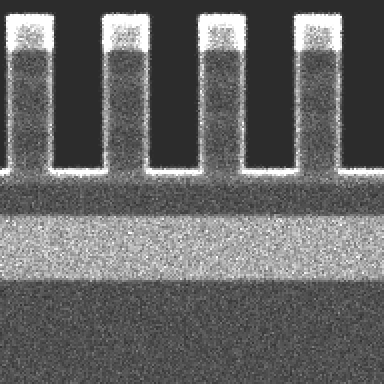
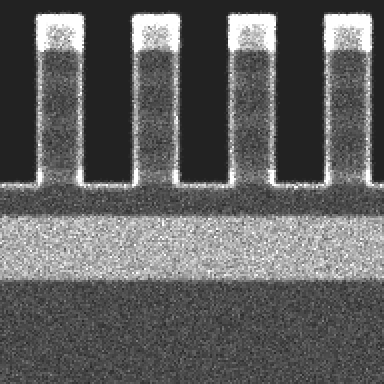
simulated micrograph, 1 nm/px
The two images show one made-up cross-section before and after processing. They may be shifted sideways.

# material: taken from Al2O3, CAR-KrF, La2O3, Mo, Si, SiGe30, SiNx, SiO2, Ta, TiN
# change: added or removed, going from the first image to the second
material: SiNx
change: removed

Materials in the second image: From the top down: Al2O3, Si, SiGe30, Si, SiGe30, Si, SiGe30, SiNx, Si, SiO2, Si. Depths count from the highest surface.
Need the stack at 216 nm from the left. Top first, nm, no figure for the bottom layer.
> empty 168, Si 32, SiO2 64, Si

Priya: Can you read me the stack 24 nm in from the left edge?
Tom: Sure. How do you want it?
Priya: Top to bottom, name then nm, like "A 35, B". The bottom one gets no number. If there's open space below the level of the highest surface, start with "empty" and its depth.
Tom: empty 168, Si 32, SiO2 64, Si